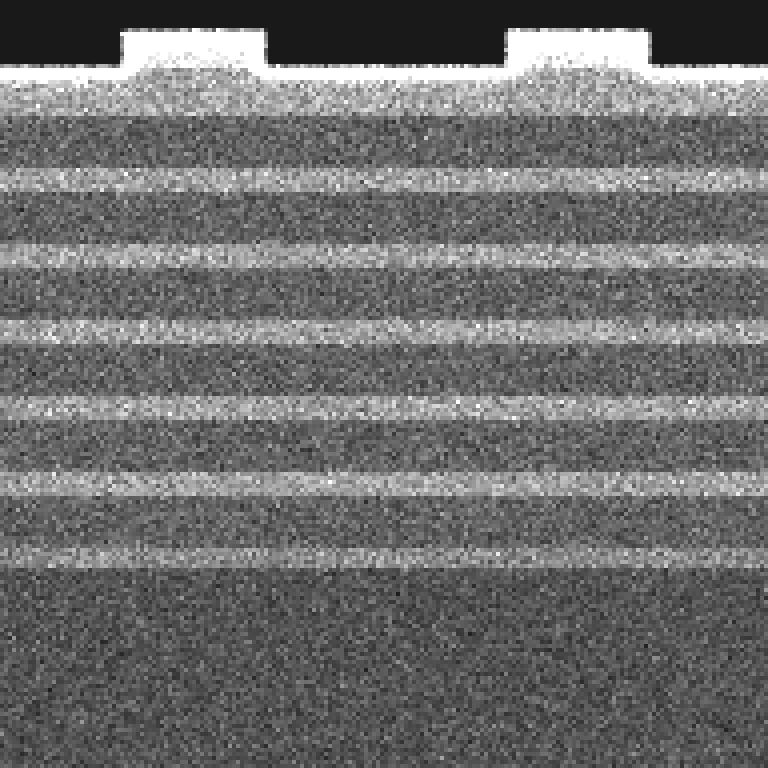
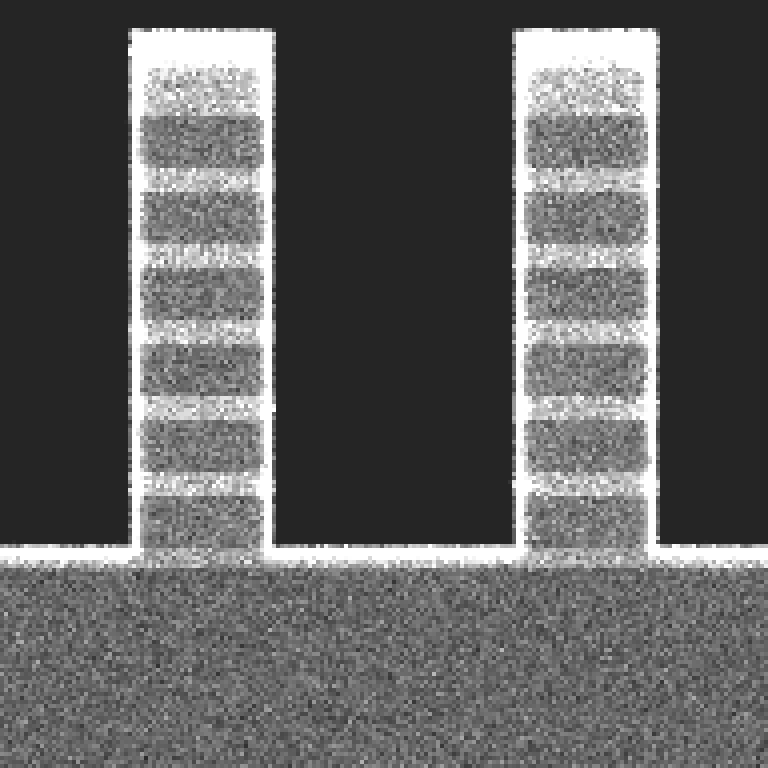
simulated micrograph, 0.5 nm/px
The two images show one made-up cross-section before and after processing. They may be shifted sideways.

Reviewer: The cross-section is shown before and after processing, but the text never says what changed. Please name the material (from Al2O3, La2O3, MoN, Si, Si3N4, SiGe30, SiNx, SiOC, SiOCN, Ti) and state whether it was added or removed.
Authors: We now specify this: Si3N4 and SiGe30, removed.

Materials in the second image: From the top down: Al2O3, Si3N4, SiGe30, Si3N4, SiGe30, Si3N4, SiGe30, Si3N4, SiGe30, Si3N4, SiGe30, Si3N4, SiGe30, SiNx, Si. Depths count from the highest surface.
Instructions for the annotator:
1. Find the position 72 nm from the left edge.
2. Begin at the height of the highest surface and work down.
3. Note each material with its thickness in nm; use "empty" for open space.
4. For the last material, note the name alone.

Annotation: Al2O3 18, Si3N4 24, SiGe30 26, Si3N4 12, SiGe30 26, Si3N4 12, SiGe30 26, Si3N4 12, SiGe30 26, Si3N4 12, SiGe30 26, Si3N4 12, SiGe30 26, SiNx 10, Si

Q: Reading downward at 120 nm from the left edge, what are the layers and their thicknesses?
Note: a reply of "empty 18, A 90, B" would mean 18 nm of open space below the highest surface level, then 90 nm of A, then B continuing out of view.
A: Al2O3 18, Si3N4 24, SiGe30 26, Si3N4 12, SiGe30 26, Si3N4 12, SiGe30 26, Si3N4 12, SiGe30 26, Si3N4 12, SiGe30 26, Si3N4 12, SiGe30 26, SiNx 10, Si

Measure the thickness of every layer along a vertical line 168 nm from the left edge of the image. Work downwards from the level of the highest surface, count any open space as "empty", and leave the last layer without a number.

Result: empty 258, SiNx 10, Si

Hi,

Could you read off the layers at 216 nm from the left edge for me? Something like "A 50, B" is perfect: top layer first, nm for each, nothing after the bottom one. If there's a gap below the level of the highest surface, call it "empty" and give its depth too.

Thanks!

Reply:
empty 258, SiNx 10, Si